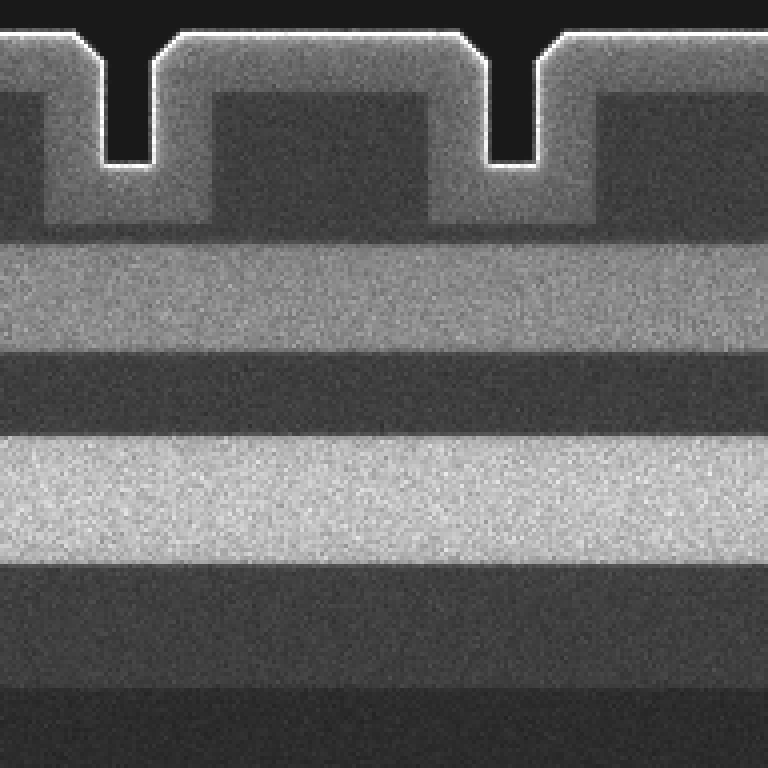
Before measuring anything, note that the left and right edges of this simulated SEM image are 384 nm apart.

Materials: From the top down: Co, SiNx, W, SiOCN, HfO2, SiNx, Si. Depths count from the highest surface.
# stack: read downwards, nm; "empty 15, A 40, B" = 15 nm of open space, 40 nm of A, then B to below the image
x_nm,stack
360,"Co 30, SiNx 76, W 54, SiOCN 42, HfO2 64, SiNx 62, Si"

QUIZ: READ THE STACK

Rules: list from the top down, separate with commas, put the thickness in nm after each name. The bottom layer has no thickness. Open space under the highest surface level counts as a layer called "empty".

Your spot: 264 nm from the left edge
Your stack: empty 66, Co 30, SiNx 10, W 54, SiOCN 42, HfO2 64, SiNx 62, Si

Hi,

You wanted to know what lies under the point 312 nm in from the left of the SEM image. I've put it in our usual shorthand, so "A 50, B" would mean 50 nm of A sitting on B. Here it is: Co 30, SiNx 76, W 54, SiOCN 42, HfO2 64, SiNx 62, Si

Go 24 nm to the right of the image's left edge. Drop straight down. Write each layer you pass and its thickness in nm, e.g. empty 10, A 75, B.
Co 96, SiNx 10, W 54, SiOCN 42, HfO2 64, SiNx 62, Si